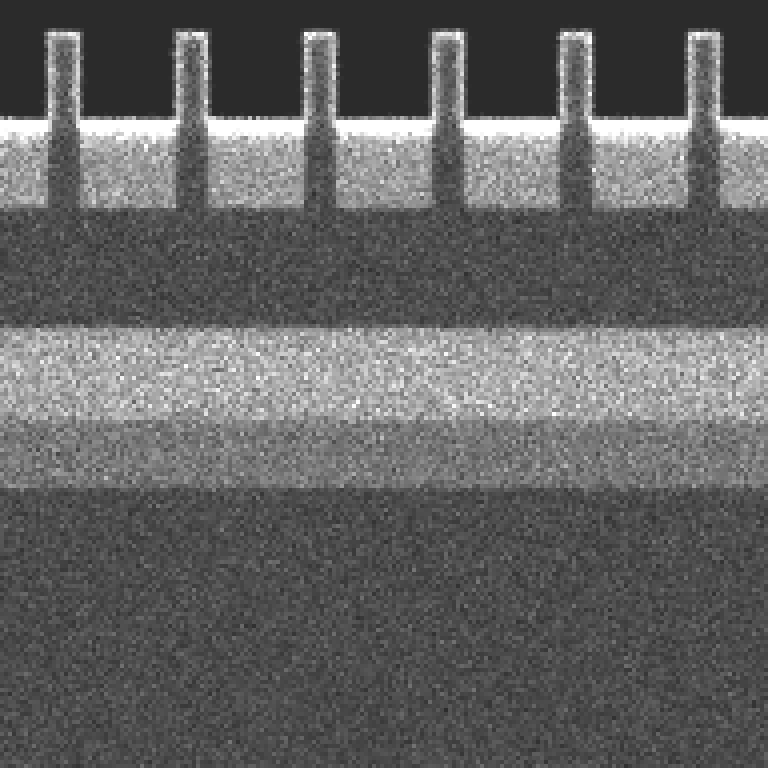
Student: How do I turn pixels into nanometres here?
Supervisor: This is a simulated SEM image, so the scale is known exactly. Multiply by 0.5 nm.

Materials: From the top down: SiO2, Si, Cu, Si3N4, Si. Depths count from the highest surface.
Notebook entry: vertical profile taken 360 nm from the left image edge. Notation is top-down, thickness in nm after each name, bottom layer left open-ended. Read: empty 44, SiO2 44, Si 60, Cu 46, Si3N4 34, Si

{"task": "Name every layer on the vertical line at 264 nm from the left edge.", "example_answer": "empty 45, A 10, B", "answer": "empty 44, SiO2 44, Si 60, Cu 46, Si3N4 34, Si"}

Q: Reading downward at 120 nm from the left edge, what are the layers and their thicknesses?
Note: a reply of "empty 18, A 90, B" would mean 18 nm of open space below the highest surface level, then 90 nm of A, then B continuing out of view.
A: empty 44, SiO2 44, Si 60, Cu 46, Si3N4 34, Si